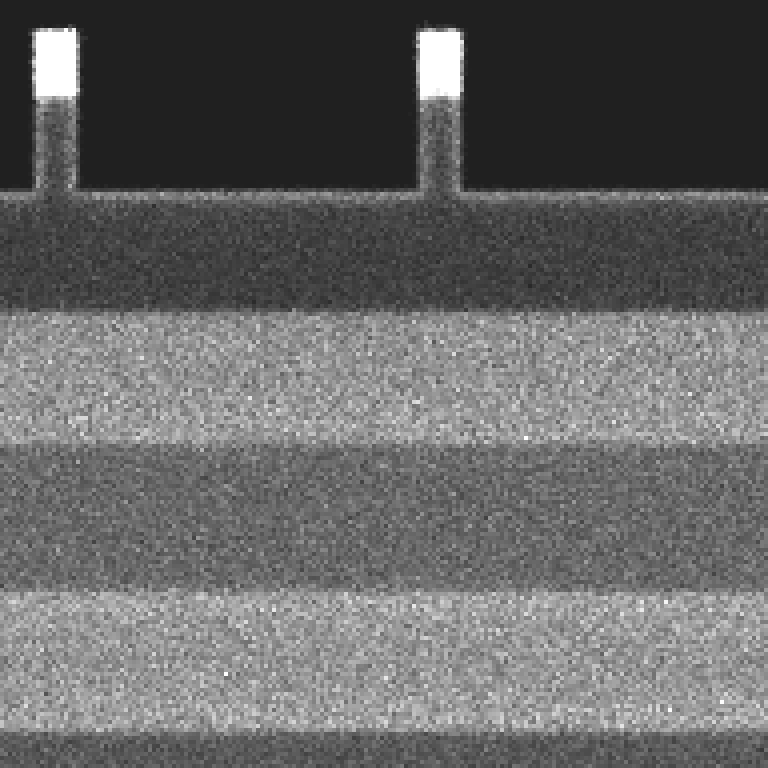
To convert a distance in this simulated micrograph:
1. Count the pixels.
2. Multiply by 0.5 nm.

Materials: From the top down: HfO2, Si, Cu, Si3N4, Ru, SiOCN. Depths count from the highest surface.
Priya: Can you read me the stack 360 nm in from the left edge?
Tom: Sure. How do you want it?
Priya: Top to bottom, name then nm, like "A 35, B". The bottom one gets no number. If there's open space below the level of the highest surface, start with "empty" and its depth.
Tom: empty 80, Si 60, Cu 66, Si3N4 74, Ru 70, SiOCN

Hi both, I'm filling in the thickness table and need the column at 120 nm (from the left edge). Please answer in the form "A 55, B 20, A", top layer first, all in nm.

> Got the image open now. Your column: empty 80, Si 60, Cu 66, Si3N4 74, Ru 70, SiOCN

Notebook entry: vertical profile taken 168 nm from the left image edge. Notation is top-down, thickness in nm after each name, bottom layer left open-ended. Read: empty 80, Si 60, Cu 66, Si3N4 74, Ru 70, SiOCN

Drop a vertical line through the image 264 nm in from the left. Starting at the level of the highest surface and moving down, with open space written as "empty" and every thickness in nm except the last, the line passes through empty 80, Si 60, Cu 66, Si3N4 74, Ru 70, SiOCN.